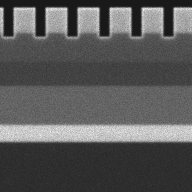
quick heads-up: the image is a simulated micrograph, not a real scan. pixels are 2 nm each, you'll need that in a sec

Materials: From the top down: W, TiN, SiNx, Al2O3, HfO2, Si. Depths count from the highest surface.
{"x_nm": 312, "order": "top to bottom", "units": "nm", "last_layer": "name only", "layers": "W 50, TiN 58, SiNx 48, Al2O3 78, HfO2 34, Si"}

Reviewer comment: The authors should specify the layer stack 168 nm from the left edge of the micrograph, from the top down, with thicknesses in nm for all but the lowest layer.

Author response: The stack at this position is W 50, TiN 58, SiNx 48, Al2O3 78, HfO2 34, Si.